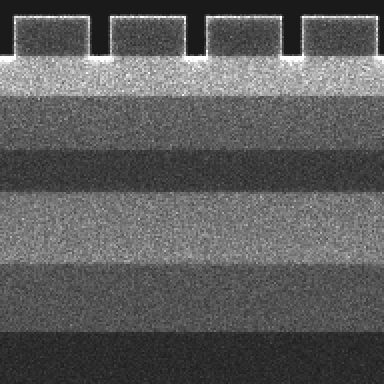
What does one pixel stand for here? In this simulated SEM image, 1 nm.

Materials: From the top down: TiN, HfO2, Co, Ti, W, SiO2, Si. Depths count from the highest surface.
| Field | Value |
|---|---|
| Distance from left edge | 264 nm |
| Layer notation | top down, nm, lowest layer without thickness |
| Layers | TiN 40, HfO2 40, Co 54, Ti 42, W 72, SiO2 68, Si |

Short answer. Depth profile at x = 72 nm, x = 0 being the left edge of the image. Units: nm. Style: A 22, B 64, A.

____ TiN 40, HfO2 40, Co 54, Ti 42, W 72, SiO2 68, Si